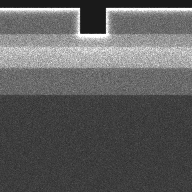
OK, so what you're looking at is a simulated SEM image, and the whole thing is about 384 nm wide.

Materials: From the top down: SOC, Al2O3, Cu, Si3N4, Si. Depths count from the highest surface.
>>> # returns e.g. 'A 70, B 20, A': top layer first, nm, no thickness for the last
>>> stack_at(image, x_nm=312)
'SOC 52, Al2O3 26, Cu 42, Si3N4 54, Si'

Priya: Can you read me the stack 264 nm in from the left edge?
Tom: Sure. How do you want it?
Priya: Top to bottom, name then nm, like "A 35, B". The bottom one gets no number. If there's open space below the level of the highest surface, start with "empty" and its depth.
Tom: SOC 52, Al2O3 26, Cu 42, Si3N4 54, Si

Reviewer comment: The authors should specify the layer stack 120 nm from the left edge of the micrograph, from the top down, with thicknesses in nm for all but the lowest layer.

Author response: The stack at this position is SOC 52, Al2O3 26, Cu 42, Si3N4 54, Si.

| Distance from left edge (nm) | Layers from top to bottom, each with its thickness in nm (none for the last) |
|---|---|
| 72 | SOC 52, Al2O3 26, Cu 42, Si3N4 54, Si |